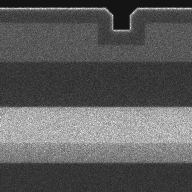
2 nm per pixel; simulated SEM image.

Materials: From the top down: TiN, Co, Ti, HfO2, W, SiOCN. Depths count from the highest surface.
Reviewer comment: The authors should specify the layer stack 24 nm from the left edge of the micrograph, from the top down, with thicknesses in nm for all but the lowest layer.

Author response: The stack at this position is TiN 30, Co 78, Ti 90, HfO2 72, W 40, SiOCN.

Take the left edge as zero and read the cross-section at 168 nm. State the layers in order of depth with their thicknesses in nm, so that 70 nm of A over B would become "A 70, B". TiN 30, Co 78, Ti 90, HfO2 72, W 40, SiOCN